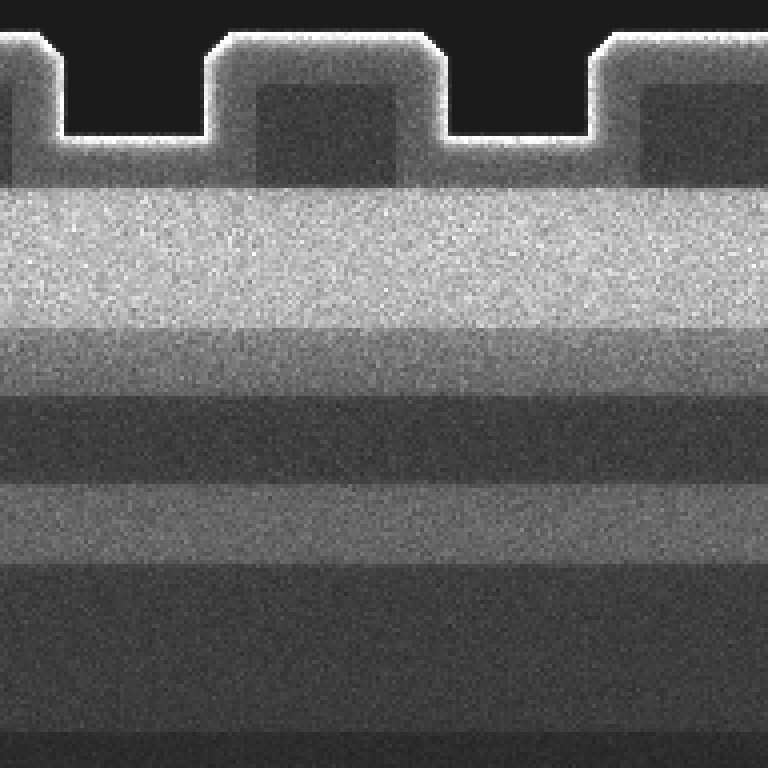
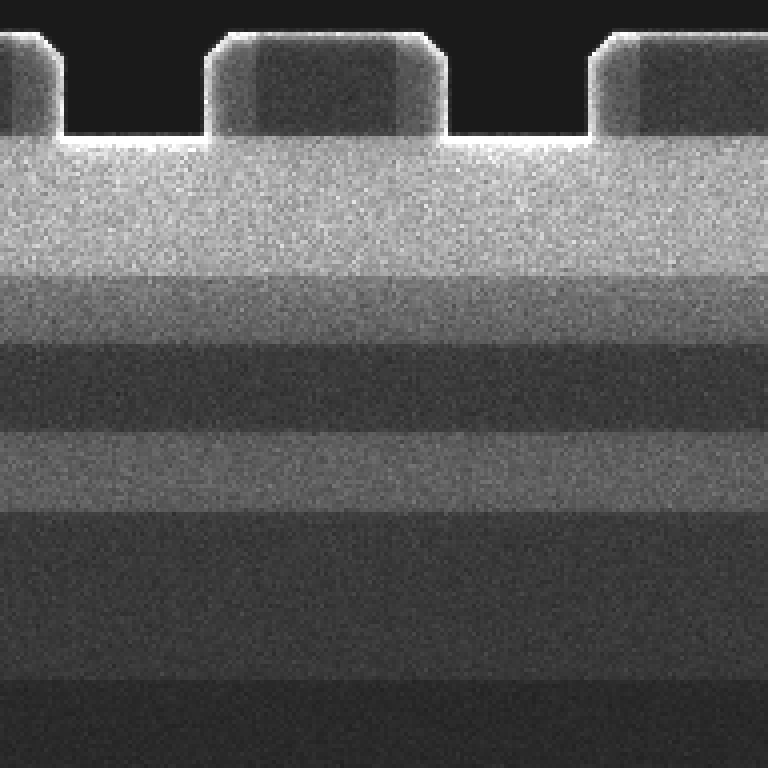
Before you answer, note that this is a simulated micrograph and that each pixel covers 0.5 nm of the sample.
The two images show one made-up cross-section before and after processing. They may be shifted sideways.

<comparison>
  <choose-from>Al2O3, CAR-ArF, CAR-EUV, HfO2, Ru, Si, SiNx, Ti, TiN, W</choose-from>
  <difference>Al2O3 removed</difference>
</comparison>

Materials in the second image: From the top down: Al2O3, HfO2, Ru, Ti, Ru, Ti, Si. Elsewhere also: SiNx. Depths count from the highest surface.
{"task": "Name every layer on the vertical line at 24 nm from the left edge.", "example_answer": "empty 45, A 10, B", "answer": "empty 6, Al2O3 46, HfO2 70, Ru 34, Ti 44, Ru 40, Ti 84, Si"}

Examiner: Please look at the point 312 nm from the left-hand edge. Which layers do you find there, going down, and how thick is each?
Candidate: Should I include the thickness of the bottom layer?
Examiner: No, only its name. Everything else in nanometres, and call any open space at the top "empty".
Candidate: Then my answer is Al2O3 52, HfO2 70, Ru 34, Ti 44, Ru 40, Ti 84, Si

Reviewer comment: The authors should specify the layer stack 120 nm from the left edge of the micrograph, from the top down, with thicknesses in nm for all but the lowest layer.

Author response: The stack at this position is Al2O3 52, HfO2 70, Ru 34, Ti 44, Ru 40, Ti 84, Si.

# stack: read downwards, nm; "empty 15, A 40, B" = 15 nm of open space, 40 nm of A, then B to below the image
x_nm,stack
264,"empty 52, HfO2 70, Ru 34, Ti 44, Ru 40, Ti 84, Si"